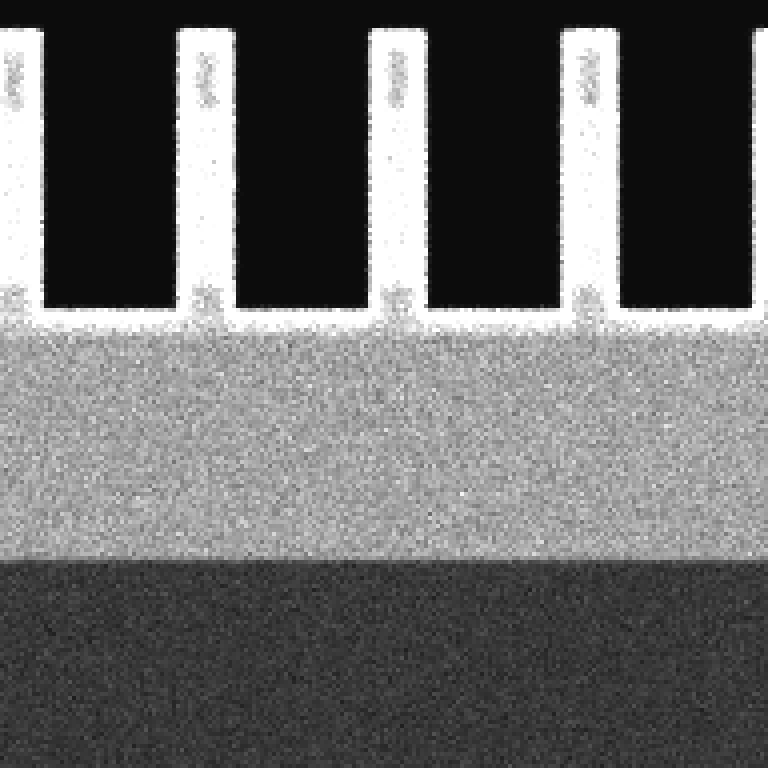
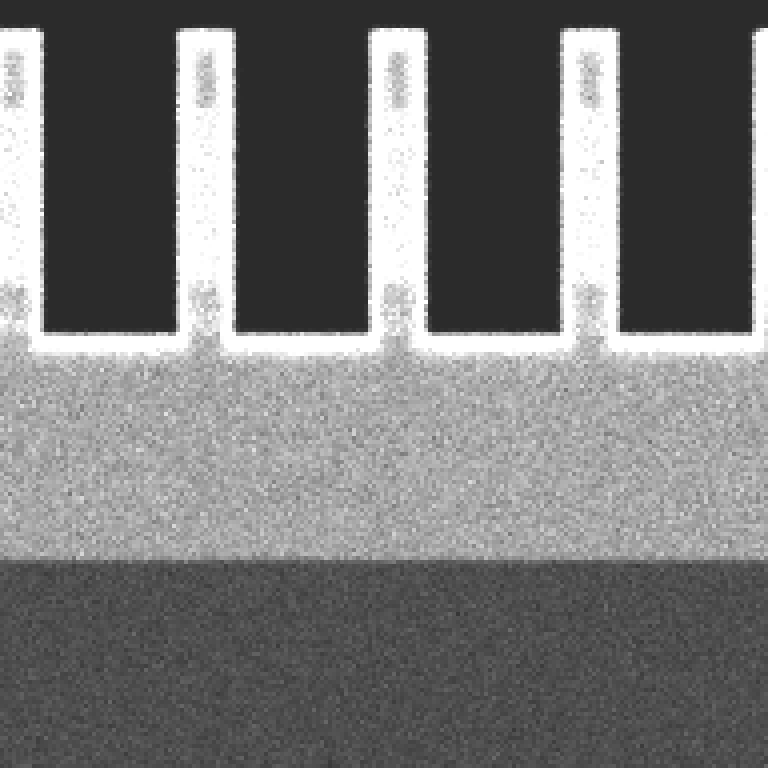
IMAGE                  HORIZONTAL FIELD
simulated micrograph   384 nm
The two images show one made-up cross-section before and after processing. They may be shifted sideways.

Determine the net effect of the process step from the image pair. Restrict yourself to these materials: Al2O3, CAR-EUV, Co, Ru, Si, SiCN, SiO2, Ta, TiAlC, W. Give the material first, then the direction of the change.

Ru: removed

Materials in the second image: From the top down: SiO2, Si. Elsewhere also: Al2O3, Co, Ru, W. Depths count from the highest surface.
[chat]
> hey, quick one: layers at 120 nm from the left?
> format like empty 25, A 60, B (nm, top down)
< empty 152, SiO2 112, Si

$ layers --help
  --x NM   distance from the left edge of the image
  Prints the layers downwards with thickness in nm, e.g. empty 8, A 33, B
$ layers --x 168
empty 152, SiO2 112, Si